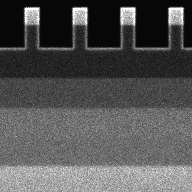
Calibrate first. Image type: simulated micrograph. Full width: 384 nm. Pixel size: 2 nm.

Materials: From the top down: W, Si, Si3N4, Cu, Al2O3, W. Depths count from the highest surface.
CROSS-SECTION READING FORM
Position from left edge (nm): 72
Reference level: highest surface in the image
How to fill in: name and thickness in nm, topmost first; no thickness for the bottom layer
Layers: W 34, Si 106, Si3N4 60, Cu 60, Al2O3 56, W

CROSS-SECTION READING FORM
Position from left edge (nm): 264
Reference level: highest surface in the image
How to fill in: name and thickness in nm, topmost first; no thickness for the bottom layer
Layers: W 34, Si 106, Si3N4 60, Cu 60, Al2O3 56, W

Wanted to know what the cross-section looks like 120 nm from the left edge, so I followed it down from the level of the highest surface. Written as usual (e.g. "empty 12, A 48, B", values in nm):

empty 80, Si 60, Si3N4 60, Cu 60, Al2O3 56, W